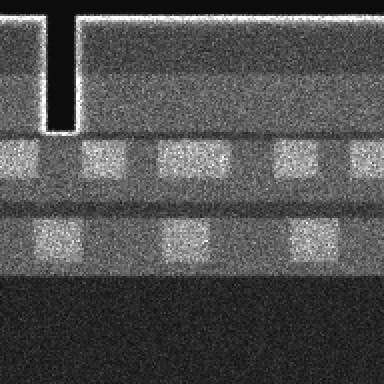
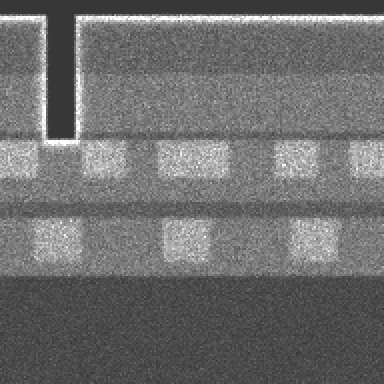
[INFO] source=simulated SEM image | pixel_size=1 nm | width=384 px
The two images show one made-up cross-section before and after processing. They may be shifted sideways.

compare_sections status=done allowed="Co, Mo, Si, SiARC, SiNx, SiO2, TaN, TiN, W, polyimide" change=removed material="SiNx"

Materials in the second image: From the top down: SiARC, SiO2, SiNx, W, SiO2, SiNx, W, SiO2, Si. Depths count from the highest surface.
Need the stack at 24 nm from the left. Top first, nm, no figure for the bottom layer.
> SiARC 58, SiO2 58, SiNx 8, W 38, SiO2 24, SiNx 16, SiO2 58, Si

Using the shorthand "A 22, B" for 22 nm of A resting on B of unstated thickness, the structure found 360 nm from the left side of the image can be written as SiARC 58, SiO2 58, SiNx 8, W 38, SiO2 24, SiNx 16, SiO2 58, Si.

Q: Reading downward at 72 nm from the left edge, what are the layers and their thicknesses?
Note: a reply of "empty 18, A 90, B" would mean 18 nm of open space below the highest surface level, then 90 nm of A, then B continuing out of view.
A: empty 124, SiO2 62, SiNx 16, W 44, SiO2 14, Si